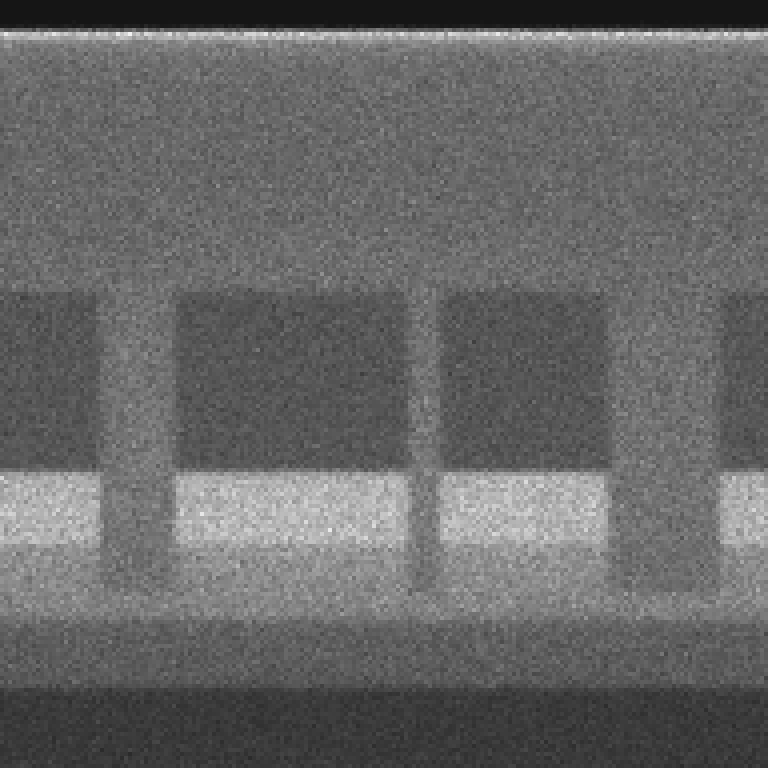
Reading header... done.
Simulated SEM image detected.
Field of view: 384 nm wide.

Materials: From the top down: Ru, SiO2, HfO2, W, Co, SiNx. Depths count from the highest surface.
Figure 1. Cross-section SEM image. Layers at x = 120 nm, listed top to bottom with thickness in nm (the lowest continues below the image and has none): Ru 130, SiO2 90, HfO2 36, W 38, Co 34, SiNx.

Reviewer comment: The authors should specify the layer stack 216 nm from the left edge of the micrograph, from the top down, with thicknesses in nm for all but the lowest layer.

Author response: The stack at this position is Ru 280, W 14, Co 34, SiNx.